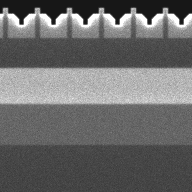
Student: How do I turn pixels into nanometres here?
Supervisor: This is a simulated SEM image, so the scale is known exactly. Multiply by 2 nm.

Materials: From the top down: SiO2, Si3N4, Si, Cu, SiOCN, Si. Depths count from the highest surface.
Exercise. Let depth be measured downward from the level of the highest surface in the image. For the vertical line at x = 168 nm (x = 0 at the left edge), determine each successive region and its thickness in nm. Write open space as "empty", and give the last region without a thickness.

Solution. empty 34, Si3N4 26, Si 60, Cu 72, SiOCN 82, Si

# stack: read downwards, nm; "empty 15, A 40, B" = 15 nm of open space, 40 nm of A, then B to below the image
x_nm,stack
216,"empty 12, SiO2 22, Si3N4 26, Si 60, Cu 72, SiOCN 82, Si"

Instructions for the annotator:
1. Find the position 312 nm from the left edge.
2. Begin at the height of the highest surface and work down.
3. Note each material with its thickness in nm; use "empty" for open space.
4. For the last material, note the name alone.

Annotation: empty 14, SiO2 20, Si3N4 26, Si 60, Cu 72, SiOCN 82, Si